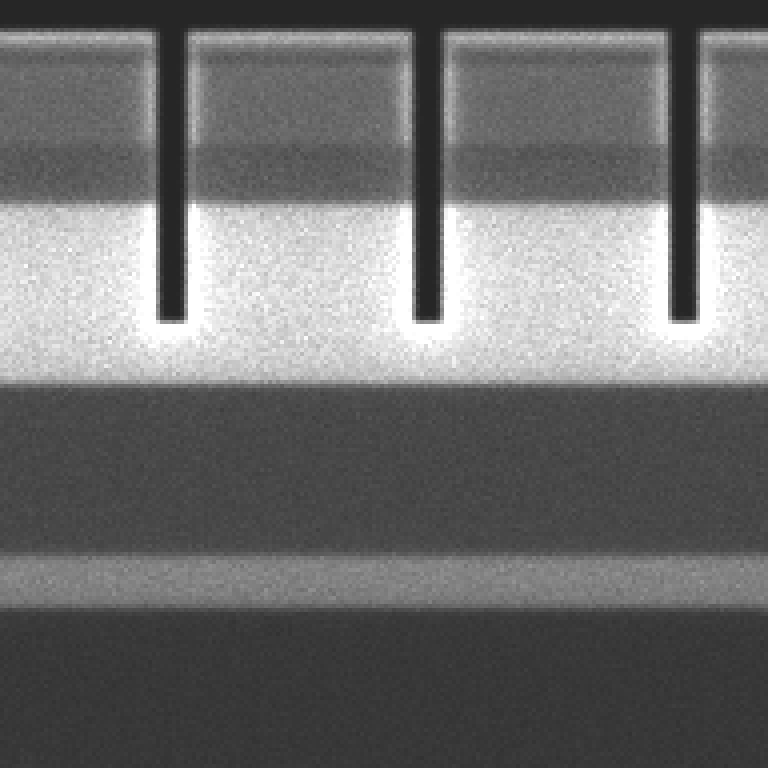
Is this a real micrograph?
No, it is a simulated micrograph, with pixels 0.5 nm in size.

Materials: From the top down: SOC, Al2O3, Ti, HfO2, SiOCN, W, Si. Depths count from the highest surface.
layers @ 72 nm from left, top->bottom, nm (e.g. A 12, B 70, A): SOC 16, Al2O3 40, Ti 30, HfO2 90, SiOCN 86, W 26, Si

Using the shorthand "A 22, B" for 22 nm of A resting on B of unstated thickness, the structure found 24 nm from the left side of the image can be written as SOC 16, Al2O3 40, Ti 30, HfO2 90, SiOCN 86, W 26, Si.